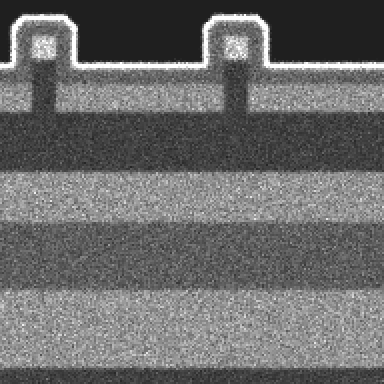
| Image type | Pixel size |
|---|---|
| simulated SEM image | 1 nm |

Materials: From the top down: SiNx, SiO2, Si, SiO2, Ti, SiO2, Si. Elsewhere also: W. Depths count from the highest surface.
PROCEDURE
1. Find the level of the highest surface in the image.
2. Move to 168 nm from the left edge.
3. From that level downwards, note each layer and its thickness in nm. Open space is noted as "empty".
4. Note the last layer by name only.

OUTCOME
empty 48, SiNx 20, SiO2 28, Si 60, SiO2 50, Ti 68, SiO2 78, Si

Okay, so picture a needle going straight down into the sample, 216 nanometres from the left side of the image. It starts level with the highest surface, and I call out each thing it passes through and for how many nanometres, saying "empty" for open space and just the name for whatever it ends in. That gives SiNx 68, SiO2 28, Si 60, SiO2 50, Ti 68, SiO2 78, Si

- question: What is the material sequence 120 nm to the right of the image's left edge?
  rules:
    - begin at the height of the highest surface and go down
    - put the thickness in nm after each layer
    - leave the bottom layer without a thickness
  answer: empty 48, SiNx 20, SiO2 28, Si 60, SiO2 50, Ti 68, SiO2 78, Si